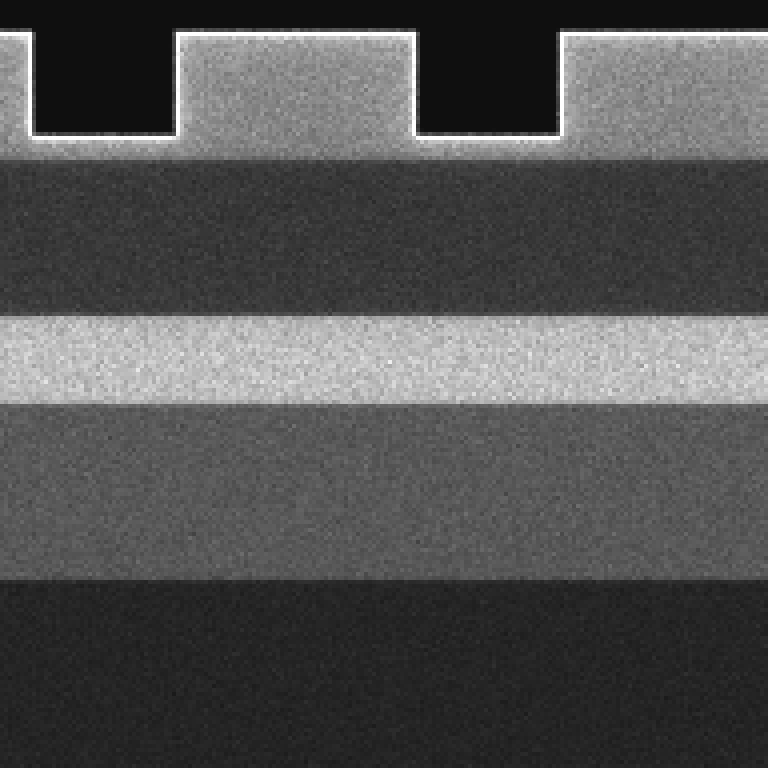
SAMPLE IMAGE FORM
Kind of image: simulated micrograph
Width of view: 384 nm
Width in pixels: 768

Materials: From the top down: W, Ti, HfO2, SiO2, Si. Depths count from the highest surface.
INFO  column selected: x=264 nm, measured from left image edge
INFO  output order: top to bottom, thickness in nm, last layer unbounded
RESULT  empty 52, W 12, Ti 78, HfO2 44, SiO2 88, Si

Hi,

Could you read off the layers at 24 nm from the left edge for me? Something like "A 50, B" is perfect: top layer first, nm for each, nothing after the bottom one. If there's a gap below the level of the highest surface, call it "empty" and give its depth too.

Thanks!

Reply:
empty 52, W 12, Ti 78, HfO2 44, SiO2 88, Si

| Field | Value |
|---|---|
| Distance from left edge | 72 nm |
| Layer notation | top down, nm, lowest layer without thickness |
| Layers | empty 52, W 12, Ti 78, HfO2 44, SiO2 88, Si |